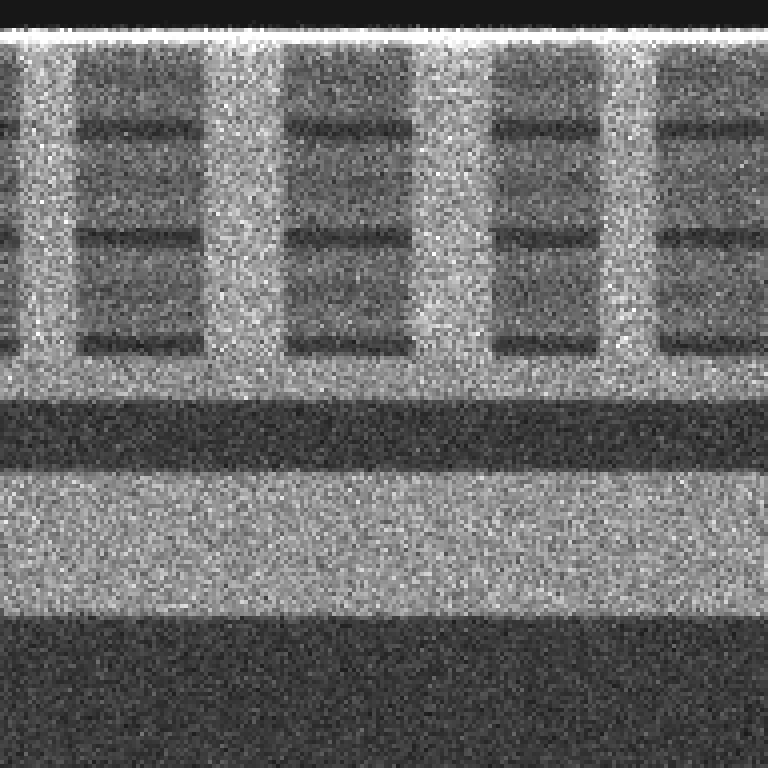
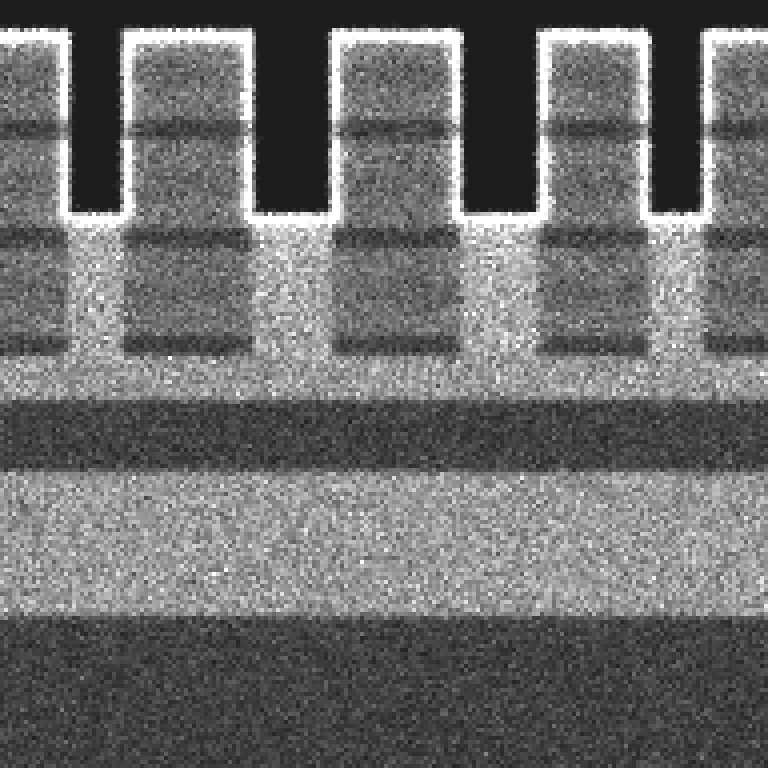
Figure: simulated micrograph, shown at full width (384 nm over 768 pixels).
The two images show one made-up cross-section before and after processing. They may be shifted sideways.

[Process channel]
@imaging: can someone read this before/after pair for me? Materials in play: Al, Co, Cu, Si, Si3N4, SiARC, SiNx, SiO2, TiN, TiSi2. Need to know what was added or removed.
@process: Co removed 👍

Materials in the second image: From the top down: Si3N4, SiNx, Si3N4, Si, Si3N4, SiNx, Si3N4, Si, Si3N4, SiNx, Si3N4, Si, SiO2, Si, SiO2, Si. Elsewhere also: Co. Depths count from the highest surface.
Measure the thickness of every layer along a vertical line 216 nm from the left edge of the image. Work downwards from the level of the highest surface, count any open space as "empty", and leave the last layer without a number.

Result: Si3N4 16, SiNx 12, Si3N4 16, Si 10, Si3N4 16, SiNx 12, Si3N4 16, Si 10, Si3N4 16, SiNx 12, Si3N4 16, Si 10, SiO2 22, Si 36, SiO2 72, Si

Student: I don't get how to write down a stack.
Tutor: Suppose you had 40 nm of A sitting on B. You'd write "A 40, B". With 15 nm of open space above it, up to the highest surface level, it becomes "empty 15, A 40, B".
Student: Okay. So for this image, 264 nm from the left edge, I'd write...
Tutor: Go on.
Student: empty 92, Co 70, SiO2 22, Si 36, SiO2 72, Si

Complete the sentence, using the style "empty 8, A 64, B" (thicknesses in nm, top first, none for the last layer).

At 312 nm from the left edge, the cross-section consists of Si3N4 16, SiNx 12, Si3N4 16, Si 10, Si3N4 16, SiNx 12, Si3N4 16, Si 10, Si3N4 16, SiNx 12, Si3N4 16, Si 10, SiO2 22, Si 36, SiO2 72, Si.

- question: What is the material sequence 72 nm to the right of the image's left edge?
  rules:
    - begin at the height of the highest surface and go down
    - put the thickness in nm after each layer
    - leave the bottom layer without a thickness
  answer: Si3N4 16, SiNx 12, Si3N4 16, Si 10, Si3N4 16, SiNx 12, Si3N4 16, Si 10, Si3N4 16, SiNx 12, Si3N4 16, Si 10, SiO2 22, Si 36, SiO2 72, Si